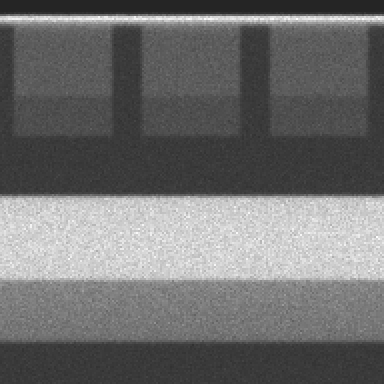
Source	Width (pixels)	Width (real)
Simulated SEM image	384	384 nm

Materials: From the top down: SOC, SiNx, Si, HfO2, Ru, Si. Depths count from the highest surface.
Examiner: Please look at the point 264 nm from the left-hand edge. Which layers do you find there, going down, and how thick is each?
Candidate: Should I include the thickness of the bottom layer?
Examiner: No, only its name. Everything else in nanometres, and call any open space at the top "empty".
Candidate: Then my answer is SOC 8, Si 172, HfO2 84, Ru 62, Si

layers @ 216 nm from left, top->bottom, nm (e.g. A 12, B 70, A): SOC 80, SiNx 40, Si 60, HfO2 84, Ru 62, Si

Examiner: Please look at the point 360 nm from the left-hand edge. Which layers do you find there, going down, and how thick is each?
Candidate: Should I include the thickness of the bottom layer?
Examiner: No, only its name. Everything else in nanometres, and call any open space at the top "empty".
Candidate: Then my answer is SOC 80, SiNx 40, Si 60, HfO2 84, Ru 62, Si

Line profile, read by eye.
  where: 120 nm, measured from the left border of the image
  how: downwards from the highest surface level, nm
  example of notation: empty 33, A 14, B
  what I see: SOC 8, Si 172, HfO2 84, Ru 62, Si